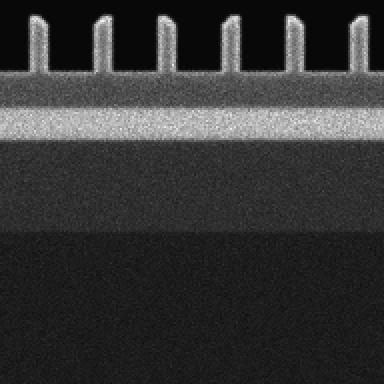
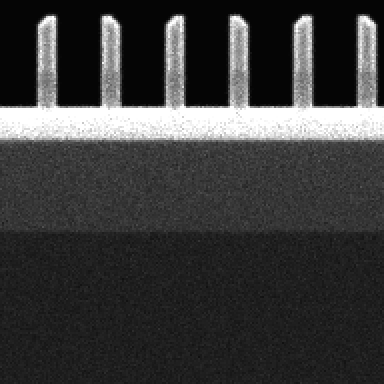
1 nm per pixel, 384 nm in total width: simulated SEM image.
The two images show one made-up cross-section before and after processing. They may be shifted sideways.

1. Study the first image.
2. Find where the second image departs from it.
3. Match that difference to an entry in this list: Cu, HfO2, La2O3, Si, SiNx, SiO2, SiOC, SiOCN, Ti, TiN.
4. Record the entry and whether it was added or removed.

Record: TiN / removed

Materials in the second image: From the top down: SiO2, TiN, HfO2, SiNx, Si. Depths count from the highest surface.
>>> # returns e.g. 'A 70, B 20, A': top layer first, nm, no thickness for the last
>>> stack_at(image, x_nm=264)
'empty 92, HfO2 32, SiNx 92, Si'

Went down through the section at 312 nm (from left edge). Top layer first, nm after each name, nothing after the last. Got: empty 92, HfO2 32, SiNx 92, Si